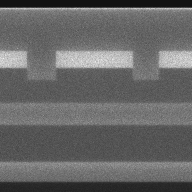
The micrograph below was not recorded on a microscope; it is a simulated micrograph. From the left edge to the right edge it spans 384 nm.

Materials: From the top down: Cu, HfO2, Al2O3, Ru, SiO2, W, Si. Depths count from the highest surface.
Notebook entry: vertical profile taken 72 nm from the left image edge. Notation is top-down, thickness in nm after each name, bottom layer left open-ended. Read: Cu 144, Al2O3 46, Ru 44, SiO2 74, W 40, Si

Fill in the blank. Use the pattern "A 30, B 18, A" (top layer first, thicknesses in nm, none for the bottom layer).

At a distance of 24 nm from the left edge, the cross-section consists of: Cu 86, HfO2 34, Al2O3 70, Ru 44, SiO2 74, W 40, Si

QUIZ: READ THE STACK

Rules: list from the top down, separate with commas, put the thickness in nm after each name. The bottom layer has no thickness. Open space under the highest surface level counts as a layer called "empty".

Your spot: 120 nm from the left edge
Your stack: Cu 86, HfO2 34, Al2O3 70, Ru 44, SiO2 74, W 40, Si